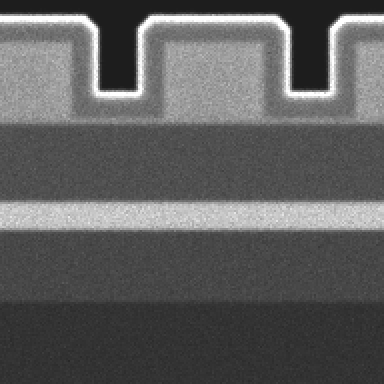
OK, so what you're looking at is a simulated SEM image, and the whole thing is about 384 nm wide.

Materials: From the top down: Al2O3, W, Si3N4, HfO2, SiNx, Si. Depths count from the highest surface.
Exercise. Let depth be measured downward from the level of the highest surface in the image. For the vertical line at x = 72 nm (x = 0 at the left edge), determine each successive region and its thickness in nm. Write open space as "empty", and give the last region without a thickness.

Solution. Al2O3 102, W 6, Si3N4 78, HfO2 28, SiNx 72, Si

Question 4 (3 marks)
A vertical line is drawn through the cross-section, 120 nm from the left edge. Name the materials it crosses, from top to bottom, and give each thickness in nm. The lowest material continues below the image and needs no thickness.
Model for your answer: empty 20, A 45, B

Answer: empty 76, Al2O3 26, W 6, Si3N4 78, HfO2 28, SiNx 72, Si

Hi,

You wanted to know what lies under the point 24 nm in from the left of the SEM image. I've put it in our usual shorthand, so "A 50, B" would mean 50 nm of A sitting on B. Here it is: Al2O3 26, W 82, Si3N4 78, HfO2 28, SiNx 72, Si